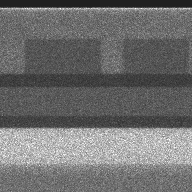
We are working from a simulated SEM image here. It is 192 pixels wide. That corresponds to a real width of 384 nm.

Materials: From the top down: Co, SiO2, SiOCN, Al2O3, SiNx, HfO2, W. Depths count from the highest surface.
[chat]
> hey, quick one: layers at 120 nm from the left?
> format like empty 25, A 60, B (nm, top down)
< Co 62, SiO2 70, SiOCN 26, Al2O3 58, SiNx 24, HfO2 72, W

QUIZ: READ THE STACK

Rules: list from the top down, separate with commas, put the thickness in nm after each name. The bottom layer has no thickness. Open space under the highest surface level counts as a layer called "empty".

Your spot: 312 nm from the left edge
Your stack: Co 62, SiO2 70, SiOCN 26, Al2O3 58, SiNx 24, HfO2 72, W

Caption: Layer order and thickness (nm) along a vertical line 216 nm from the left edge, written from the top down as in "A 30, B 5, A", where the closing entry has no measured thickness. Co 132, SiOCN 26, Al2O3 58, SiNx 24, HfO2 72, W